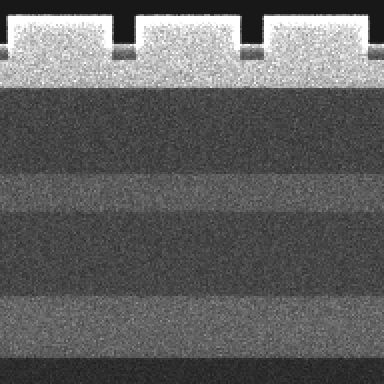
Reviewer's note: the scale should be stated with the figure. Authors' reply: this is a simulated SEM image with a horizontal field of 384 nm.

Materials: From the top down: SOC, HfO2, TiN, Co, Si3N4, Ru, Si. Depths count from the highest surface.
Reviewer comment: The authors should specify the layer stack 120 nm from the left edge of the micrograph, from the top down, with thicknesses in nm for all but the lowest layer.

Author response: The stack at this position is empty 28, SOC 16, HfO2 28, TiN 86, Co 38, Si3N4 84, Ru 62, Si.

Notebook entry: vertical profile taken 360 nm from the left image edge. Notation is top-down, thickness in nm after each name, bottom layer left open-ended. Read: HfO2 72, TiN 86, Co 38, Si3N4 84, Ru 62, Si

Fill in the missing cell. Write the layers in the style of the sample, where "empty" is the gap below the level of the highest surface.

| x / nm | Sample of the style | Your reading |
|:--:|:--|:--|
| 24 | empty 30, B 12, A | HfO2 72, TiN 86, Co 38, Si3N4 84, Ru 62, Si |